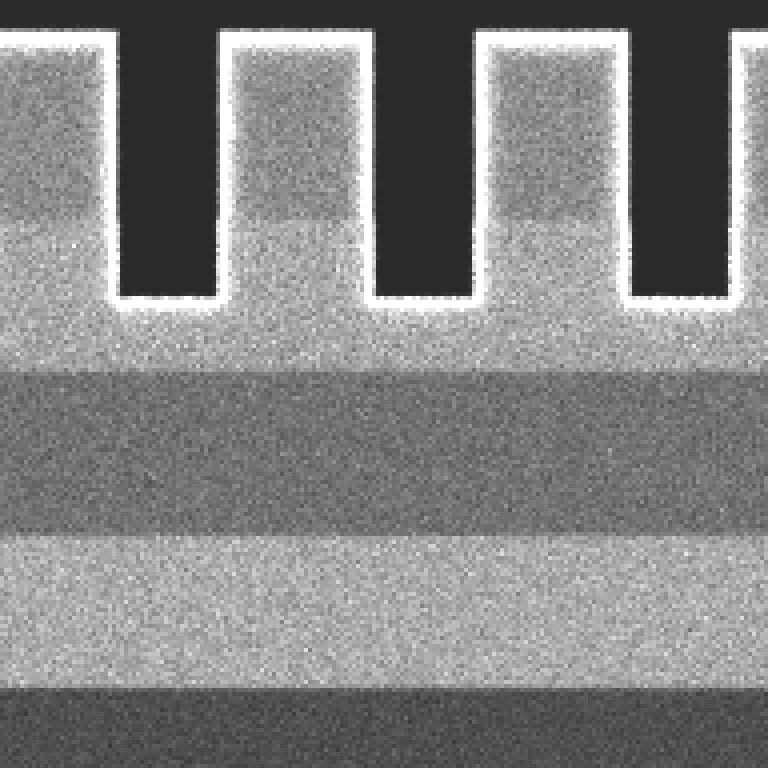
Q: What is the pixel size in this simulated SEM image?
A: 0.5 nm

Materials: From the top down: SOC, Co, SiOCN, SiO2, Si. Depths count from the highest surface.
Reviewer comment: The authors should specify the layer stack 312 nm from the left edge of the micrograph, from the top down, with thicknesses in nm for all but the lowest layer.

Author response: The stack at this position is SOC 94, Co 76, SiOCN 82, SiO2 76, Si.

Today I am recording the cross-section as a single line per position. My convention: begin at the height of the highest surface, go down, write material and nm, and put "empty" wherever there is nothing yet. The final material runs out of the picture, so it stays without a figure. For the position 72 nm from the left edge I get empty 134, Co 36, SiOCN 82, SiO2 76, Si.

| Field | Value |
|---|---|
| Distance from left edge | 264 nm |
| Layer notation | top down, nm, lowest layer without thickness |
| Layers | SOC 94, Co 76, SiOCN 82, SiO2 76, Si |